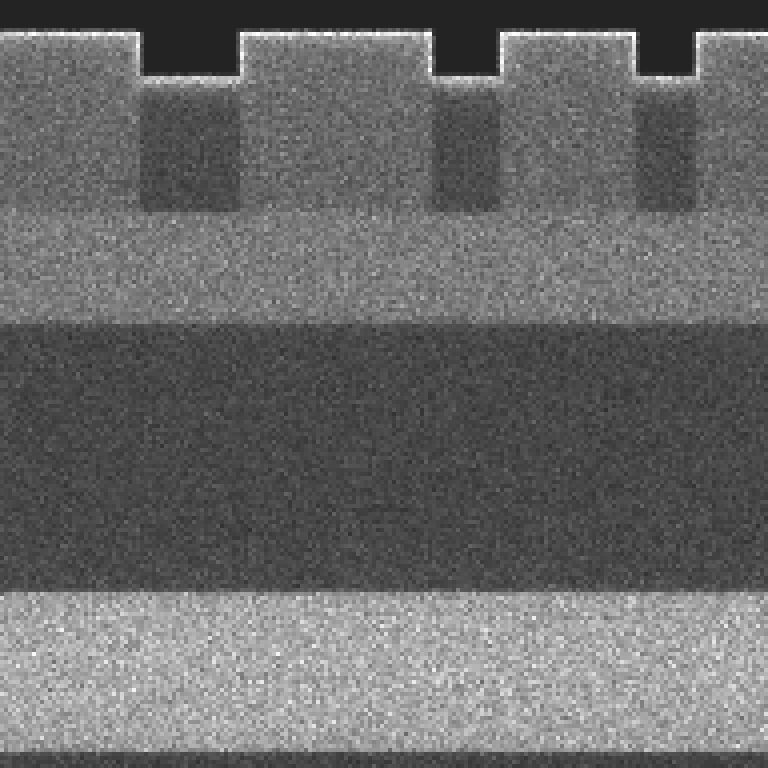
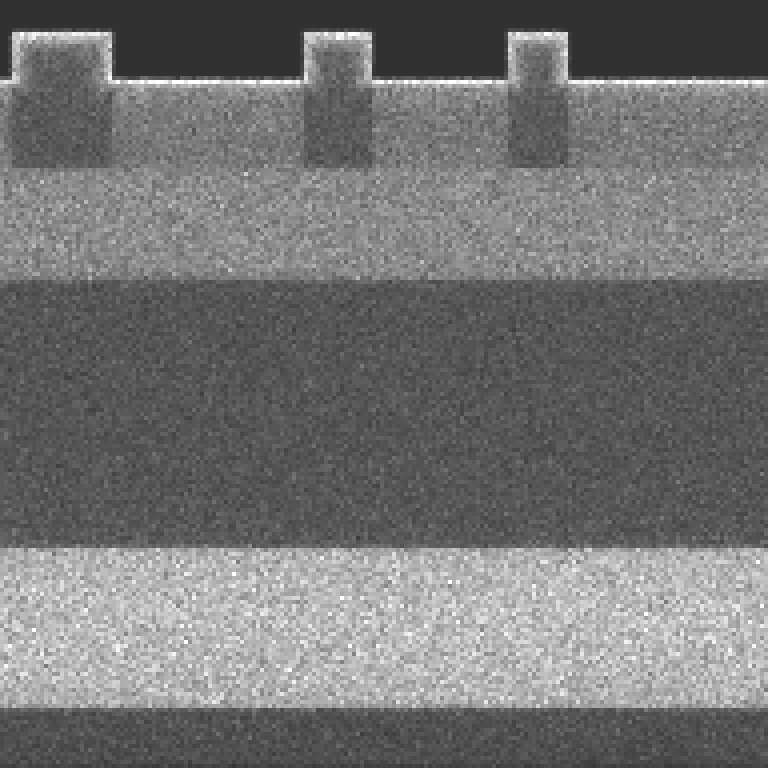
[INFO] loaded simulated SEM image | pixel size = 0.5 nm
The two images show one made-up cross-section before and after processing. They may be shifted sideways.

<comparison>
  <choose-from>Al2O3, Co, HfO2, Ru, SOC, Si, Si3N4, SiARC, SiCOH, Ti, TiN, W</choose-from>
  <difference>Ru removed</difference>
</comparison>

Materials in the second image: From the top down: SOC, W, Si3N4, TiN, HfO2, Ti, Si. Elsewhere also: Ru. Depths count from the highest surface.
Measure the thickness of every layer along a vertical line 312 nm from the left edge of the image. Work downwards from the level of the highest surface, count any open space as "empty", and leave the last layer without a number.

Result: empty 24, Ru 44, W 56, Si3N4 84, TiN 50, HfO2 80, Ti 28, Si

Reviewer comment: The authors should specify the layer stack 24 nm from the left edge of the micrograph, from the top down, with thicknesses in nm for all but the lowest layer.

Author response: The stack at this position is SOC 68, W 56, Si3N4 84, TiN 50, HfO2 80, Ti 28, Si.